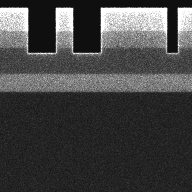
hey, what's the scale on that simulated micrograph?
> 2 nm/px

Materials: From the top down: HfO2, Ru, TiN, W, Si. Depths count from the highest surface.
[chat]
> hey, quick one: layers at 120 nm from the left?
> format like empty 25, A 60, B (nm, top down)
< HfO2 46, Ru 34, TiN 52, W 36, Si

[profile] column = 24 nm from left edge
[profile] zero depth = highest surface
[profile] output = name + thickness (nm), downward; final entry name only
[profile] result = HfO2 46, Ru 34, TiN 52, W 36, Si